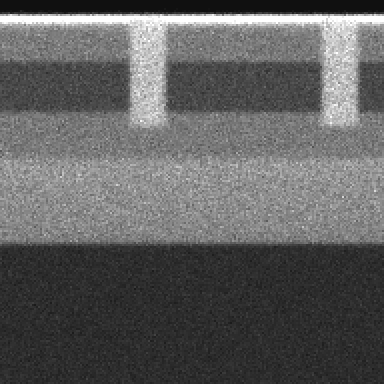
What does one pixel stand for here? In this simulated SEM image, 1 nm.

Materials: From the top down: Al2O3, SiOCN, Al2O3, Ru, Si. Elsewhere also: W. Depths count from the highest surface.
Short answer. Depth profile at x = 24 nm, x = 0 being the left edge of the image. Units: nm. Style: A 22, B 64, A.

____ Al2O3 46, SiOCN 50, Al2O3 46, Ru 86, Si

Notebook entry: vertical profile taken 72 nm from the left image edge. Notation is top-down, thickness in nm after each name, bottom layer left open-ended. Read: Al2O3 46, SiOCN 50, Al2O3 46, Ru 86, Si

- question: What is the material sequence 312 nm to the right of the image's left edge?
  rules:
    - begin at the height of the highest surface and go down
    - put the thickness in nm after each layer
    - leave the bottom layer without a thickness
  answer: Al2O3 46, SiOCN 50, Al2O3 46, Ru 86, Si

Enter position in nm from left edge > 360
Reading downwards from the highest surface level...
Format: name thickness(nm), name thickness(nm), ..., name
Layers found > Al2O3 46, SiOCN 50, Al2O3 46, Ru 86, Si